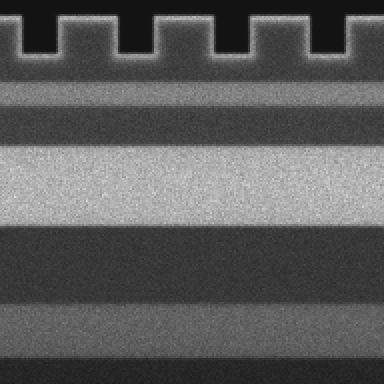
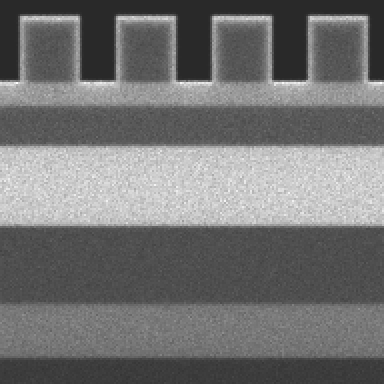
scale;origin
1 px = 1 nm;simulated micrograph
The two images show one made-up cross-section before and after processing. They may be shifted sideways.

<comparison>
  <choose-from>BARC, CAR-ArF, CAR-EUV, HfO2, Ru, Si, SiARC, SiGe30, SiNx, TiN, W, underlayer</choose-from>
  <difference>underlayer removed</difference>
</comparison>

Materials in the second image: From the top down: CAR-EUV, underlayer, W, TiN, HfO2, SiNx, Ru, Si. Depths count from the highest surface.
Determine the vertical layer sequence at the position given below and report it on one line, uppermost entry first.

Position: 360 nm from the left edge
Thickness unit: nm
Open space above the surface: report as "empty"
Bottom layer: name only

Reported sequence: CAR-EUV 38, underlayer 28, W 24, TiN 40, HfO2 80, SiNx 78, Ru 54, Si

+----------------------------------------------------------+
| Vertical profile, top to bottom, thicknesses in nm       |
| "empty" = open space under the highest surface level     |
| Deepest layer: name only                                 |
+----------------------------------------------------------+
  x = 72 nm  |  CAR-EUV 38, underlayer 28, W 24, TiN 40, HfO2 80, SiNx 78, Ru 54, Si